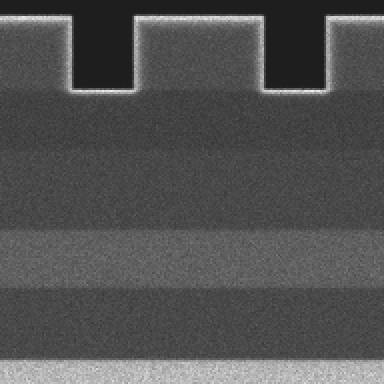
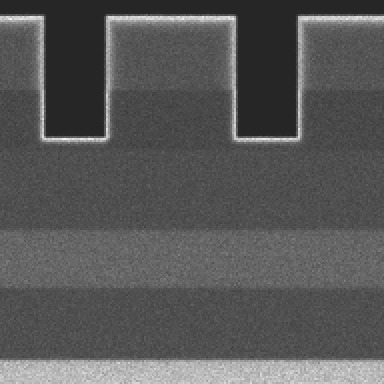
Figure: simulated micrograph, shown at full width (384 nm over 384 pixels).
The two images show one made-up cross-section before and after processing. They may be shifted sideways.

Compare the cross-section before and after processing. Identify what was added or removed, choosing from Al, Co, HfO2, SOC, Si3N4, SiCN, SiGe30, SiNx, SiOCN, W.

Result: SiNx removed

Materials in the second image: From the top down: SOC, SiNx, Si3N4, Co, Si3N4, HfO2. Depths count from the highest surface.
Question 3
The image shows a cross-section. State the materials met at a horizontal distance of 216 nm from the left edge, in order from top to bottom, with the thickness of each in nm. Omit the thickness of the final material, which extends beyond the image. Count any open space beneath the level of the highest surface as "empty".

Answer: SOC 74, SiNx 60, Si3N4 80, Co 58, Si3N4 72, HfO2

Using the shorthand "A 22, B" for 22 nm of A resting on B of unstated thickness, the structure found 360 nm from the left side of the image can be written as SOC 74, SiNx 60, Si3N4 80, Co 58, Si3N4 72, HfO2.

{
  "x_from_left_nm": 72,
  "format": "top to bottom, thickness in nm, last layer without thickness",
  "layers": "empty 122, SiNx 12, Si3N4 80, Co 58, Si3N4 72, HfO2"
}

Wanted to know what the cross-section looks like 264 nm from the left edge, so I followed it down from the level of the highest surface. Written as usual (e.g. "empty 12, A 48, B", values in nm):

empty 122, SiNx 12, Si3N4 80, Co 58, Si3N4 72, HfO2